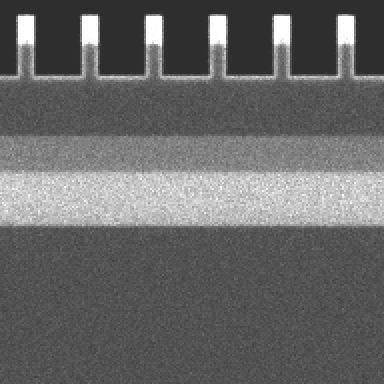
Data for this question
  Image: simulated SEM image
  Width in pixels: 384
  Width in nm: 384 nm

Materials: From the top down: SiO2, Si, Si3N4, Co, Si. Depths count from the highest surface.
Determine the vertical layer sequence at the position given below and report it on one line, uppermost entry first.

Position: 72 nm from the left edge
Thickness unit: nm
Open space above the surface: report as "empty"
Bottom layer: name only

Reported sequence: empty 60, Si 60, Si3N4 36, Co 54, Si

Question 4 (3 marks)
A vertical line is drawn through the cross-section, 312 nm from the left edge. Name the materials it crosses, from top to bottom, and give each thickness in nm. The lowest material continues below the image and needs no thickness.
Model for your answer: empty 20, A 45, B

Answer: empty 60, Si 60, Si3N4 36, Co 54, Si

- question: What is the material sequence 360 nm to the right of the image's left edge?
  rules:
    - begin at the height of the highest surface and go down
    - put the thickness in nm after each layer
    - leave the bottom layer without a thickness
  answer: empty 60, Si 60, Si3N4 36, Co 54, Si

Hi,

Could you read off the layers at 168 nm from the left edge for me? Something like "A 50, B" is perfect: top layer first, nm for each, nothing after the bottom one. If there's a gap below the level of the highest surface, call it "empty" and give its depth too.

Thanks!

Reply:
empty 60, Si 60, Si3N4 36, Co 54, Si